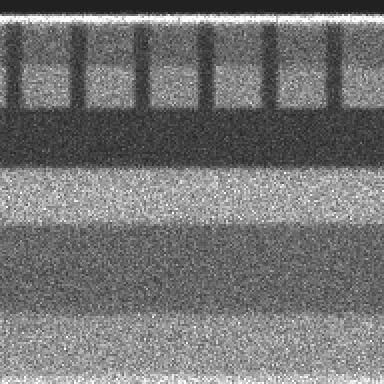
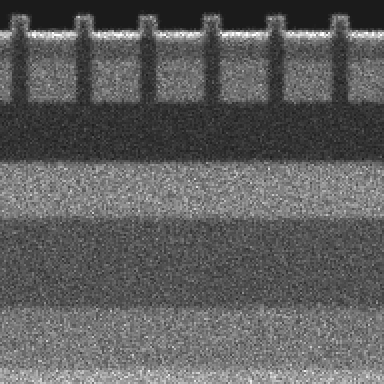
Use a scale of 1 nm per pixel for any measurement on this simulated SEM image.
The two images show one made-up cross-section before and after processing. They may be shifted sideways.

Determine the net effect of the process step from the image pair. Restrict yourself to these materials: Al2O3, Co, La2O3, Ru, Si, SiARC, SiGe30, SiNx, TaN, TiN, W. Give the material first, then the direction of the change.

SiARC: removed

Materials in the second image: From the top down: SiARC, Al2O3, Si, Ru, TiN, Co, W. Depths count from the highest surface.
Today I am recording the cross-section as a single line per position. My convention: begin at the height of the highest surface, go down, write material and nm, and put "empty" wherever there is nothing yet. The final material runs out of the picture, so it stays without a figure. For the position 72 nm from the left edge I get empty 16, SiARC 28, Al2O3 42, Si 60, Ru 56, TiN 90, Co 62, W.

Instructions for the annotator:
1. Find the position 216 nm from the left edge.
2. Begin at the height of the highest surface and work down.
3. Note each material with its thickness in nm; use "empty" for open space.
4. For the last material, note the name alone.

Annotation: Si 146, Ru 56, TiN 90, Co 62, W